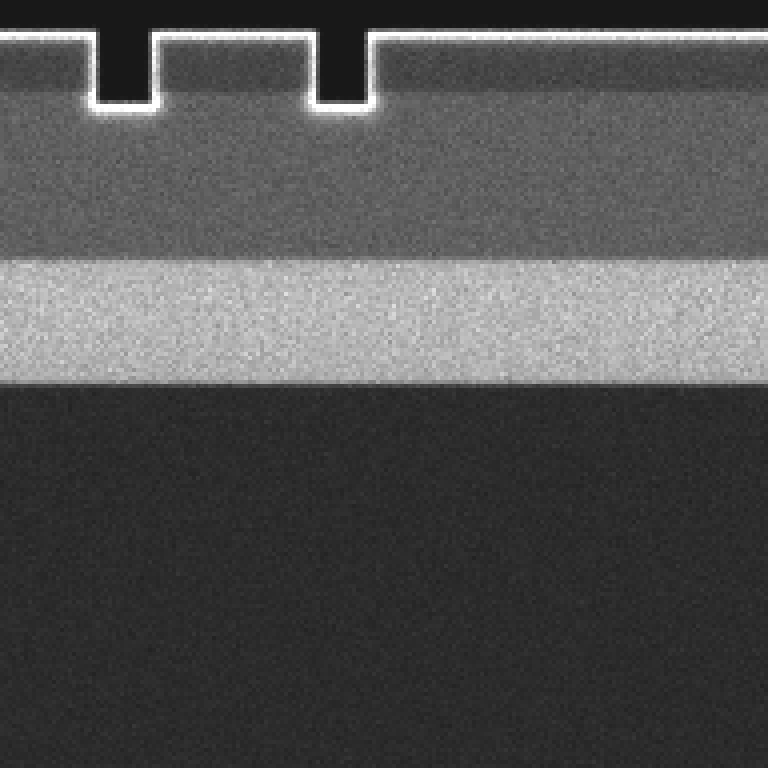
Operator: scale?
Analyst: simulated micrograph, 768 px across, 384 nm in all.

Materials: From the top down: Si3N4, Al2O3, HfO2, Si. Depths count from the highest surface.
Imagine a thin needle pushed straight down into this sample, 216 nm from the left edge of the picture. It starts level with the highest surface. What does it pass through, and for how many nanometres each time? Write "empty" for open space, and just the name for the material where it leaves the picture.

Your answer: Si3N4 30, Al2O3 84, HfO2 62, Si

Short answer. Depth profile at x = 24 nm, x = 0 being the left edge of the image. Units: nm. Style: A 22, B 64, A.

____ Si3N4 30, Al2O3 84, HfO2 62, Si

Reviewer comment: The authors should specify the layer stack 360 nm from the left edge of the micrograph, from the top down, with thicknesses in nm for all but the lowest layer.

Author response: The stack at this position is Si3N4 30, Al2O3 84, HfO2 62, Si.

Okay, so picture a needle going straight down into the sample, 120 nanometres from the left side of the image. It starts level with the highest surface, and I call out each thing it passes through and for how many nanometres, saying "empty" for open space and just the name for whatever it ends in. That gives Si3N4 30, Al2O3 84, HfO2 62, Si